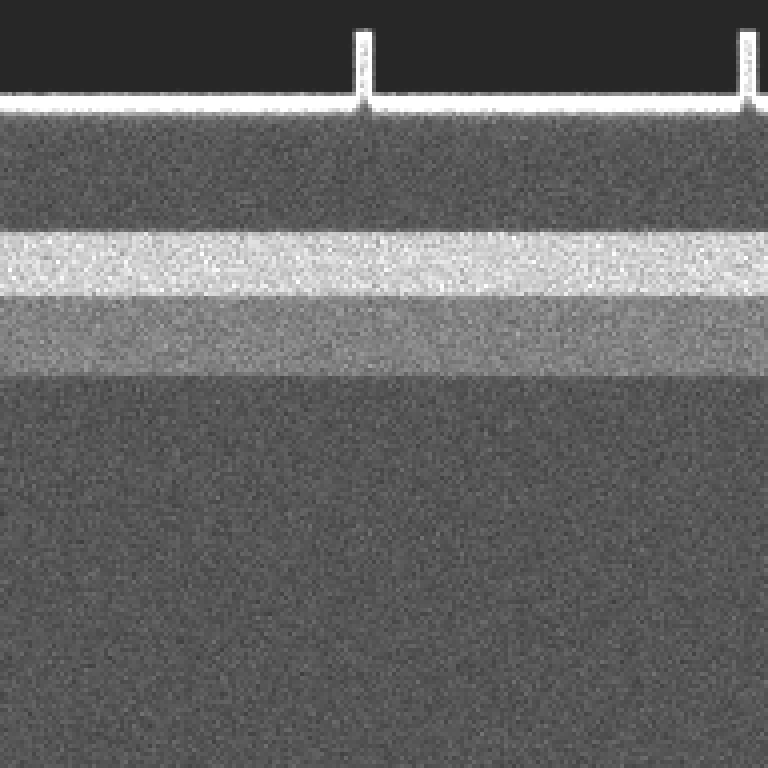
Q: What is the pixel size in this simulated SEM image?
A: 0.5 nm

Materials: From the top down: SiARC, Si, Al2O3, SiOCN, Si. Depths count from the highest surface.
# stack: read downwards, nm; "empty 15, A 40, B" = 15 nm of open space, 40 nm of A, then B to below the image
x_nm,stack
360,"empty 32, SiARC 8, Si 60, Al2O3 32, SiOCN 40, Si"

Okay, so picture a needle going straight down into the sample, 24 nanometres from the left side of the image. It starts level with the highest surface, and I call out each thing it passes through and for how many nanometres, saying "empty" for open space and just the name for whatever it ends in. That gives empty 32, SiARC 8, Si 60, Al2O3 32, SiOCN 40, Si